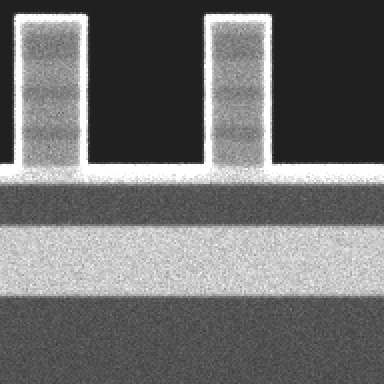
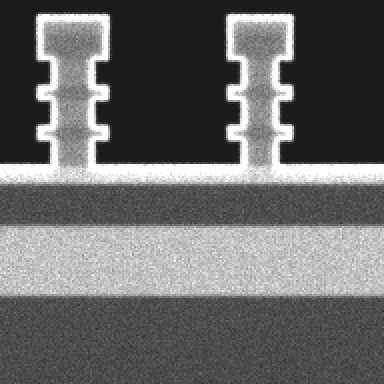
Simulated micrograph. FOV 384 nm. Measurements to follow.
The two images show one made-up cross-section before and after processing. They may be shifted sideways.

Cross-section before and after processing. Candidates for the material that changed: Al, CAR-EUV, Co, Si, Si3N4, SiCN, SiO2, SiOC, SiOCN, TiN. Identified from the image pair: Si3N4 (removed).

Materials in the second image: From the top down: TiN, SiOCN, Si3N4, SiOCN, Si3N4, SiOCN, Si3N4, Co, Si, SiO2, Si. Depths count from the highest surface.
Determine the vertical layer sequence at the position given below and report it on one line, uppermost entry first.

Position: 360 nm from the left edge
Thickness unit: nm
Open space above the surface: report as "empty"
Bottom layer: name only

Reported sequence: empty 150, Co 18, Si 42, SiO2 70, Si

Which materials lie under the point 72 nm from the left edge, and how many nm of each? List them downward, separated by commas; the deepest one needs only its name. TiN 18, SiOCN 26, Si3N4 26, SiOCN 14, Si3N4 26, SiOCN 14, Si3N4 26, Co 18, Si 42, SiO2 70, Si